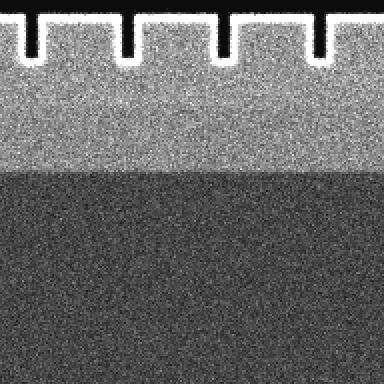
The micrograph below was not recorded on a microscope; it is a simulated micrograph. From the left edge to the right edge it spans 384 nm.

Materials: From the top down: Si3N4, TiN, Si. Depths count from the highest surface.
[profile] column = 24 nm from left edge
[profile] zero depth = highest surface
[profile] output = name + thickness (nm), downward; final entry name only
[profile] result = empty 44, Si3N4 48, TiN 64, Si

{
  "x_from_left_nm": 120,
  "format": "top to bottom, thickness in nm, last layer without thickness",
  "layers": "empty 44, Si3N4 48, TiN 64, Si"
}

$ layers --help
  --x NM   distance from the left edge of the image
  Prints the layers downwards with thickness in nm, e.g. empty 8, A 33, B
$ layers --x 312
empty 44, Si3N4 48, TiN 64, Si